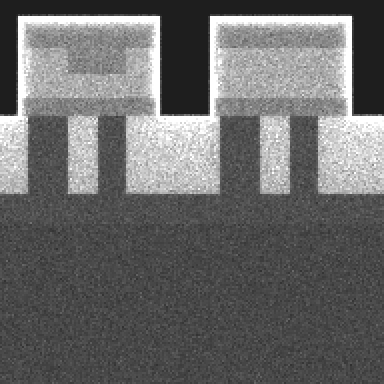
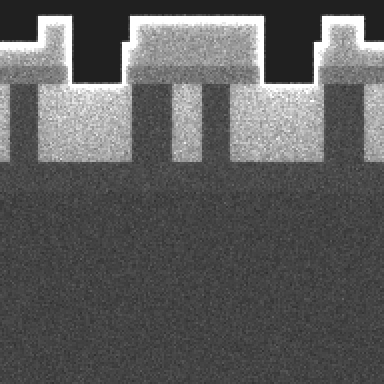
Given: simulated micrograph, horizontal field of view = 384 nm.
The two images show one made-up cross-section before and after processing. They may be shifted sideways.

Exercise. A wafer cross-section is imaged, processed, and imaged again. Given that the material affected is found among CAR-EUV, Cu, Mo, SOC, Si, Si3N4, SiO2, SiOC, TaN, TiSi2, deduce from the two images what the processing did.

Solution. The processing removed SOC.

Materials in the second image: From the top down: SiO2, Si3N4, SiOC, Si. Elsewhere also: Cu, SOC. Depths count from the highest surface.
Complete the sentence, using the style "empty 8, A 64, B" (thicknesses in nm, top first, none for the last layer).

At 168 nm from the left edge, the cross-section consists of SiO2 50, Si3N4 18, SiOC 108, Si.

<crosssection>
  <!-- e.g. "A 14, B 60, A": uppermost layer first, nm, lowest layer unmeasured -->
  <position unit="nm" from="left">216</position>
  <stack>SiO2 50, Si3N4 18, SiOC 108, Si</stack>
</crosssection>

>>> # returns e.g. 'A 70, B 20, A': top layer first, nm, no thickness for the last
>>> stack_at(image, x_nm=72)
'empty 68, Cu 78, SiOC 30, Si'